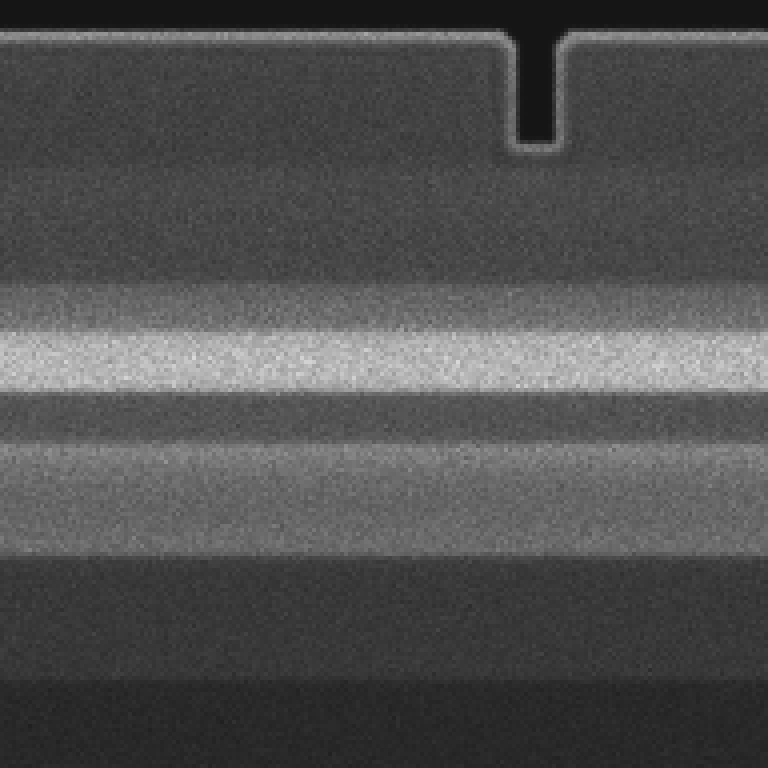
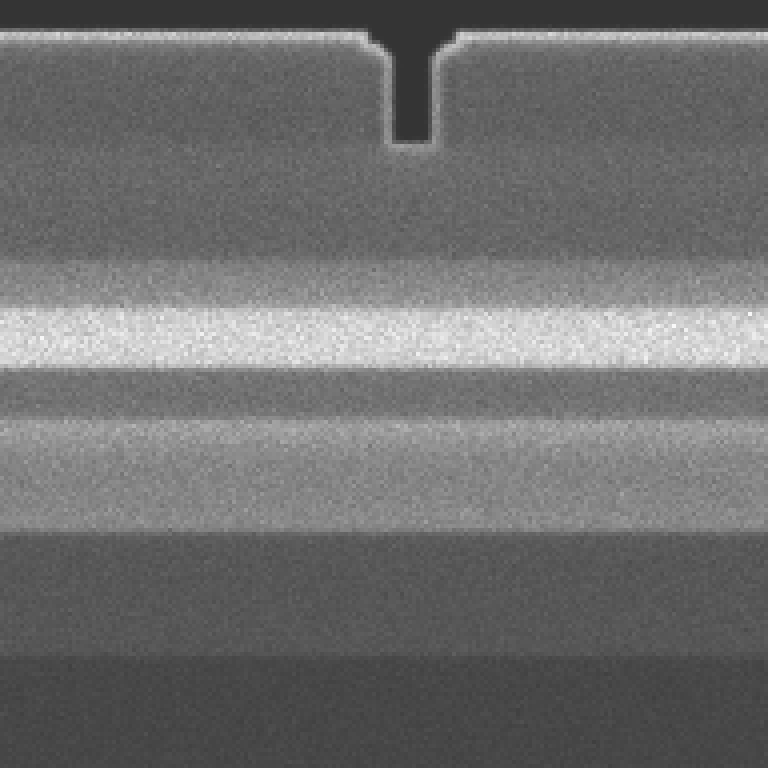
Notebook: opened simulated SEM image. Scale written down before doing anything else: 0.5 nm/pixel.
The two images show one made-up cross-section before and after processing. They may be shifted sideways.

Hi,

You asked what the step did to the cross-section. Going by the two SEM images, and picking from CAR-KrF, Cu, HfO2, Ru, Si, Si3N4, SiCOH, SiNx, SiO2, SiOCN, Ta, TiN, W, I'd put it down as SiOCN, removed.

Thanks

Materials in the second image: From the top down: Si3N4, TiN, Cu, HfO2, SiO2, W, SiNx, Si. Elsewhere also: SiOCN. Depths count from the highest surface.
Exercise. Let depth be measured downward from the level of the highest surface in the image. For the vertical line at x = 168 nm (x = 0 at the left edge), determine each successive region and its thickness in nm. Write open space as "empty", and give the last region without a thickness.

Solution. Si3N4 56, TiN 58, Cu 24, HfO2 30, SiO2 26, W 56, SiNx 62, Si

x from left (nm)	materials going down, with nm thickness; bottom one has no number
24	Si3N4 56, TiN 58, Cu 24, HfO2 30, SiO2 26, W 56, SiNx 62, Si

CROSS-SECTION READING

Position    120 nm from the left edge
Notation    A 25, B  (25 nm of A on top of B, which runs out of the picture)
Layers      Si3N4 56, TiN 58, Cu 24, HfO2 30, SiO2 26, W 56, SiNx 62, Si